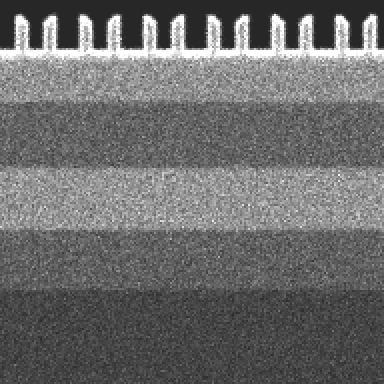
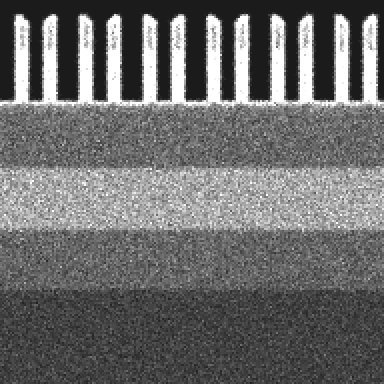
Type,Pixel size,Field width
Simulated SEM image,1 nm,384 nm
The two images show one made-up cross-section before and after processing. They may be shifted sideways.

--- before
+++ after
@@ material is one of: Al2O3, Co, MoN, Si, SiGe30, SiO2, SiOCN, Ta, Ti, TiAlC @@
SiO2 removed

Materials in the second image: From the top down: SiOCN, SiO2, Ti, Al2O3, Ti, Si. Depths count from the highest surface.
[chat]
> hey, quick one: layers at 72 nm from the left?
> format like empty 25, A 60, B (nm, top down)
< empty 86, Ti 66, Al2O3 62, Ti 60, Si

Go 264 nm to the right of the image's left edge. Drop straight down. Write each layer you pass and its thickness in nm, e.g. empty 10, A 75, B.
empty 86, Ti 66, Al2O3 62, Ti 60, Si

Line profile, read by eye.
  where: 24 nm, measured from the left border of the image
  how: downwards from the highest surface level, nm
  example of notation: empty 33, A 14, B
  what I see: empty 4, SiOCN 30, SiO2 52, Ti 66, Al2O3 62, Ti 60, Si